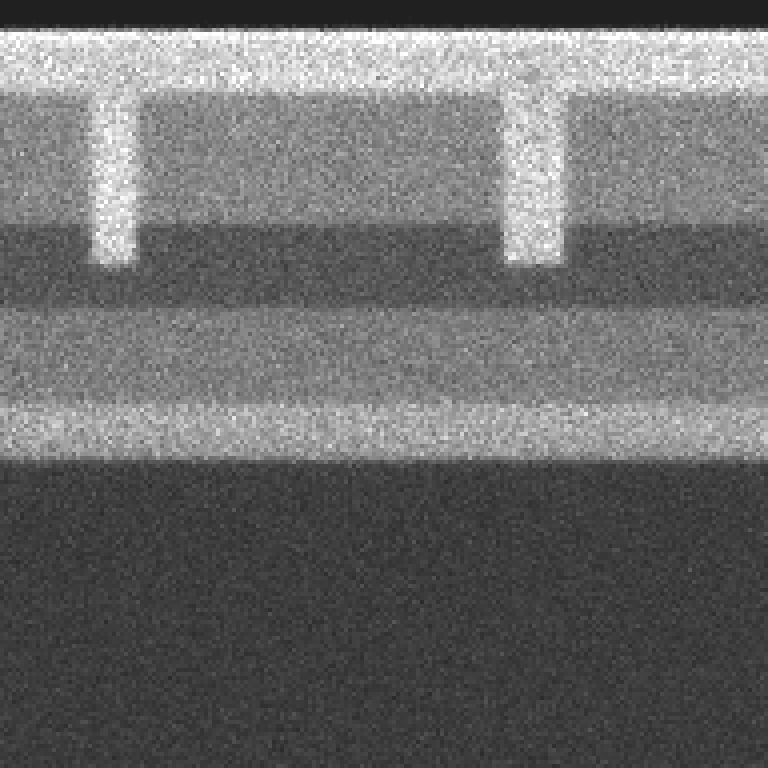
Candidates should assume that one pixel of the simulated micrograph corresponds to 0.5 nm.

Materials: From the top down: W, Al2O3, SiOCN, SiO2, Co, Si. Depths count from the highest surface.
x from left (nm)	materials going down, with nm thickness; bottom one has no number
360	W 30, Al2O3 66, SiOCN 42, SiO2 48, Co 28, Si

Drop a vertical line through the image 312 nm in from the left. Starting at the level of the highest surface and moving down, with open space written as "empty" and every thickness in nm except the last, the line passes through W 30, Al2O3 66, SiOCN 42, SiO2 48, Co 28, Si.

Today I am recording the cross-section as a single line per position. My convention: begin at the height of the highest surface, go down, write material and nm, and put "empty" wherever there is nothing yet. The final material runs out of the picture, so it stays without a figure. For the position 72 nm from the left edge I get W 30, Al2O3 66, SiOCN 42, SiO2 48, Co 28, Si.